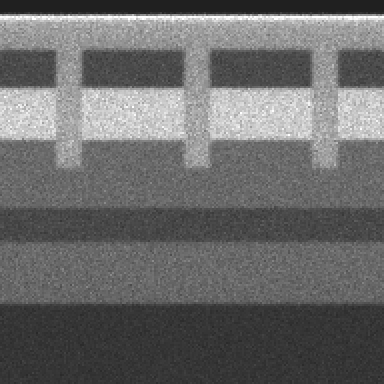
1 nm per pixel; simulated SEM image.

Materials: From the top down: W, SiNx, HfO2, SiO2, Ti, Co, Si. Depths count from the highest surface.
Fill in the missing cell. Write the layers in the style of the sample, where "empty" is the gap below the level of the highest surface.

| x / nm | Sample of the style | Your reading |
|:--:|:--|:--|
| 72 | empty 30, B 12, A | W 152, SiO2 40, Ti 34, Co 62, Si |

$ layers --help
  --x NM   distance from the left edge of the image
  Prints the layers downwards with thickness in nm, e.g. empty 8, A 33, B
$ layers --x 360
W 34, SiNx 38, HfO2 52, SiO2 68, Ti 34, Co 62, Si